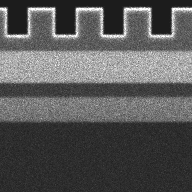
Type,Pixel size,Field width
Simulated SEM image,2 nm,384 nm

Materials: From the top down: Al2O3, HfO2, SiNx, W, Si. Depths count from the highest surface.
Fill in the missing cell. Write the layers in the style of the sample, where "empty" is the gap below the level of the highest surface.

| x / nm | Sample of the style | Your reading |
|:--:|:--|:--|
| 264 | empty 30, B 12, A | Al2O3 86, HfO2 64, SiNx 28, W 50, Si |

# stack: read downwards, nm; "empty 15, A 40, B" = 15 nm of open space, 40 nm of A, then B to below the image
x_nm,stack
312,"empty 54, Al2O3 32, HfO2 64, SiNx 28, W 50, Si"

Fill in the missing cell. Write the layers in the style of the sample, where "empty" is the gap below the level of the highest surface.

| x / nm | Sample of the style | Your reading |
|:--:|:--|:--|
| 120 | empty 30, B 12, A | empty 54, Al2O3 32, HfO2 64, SiNx 28, W 50, Si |